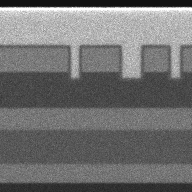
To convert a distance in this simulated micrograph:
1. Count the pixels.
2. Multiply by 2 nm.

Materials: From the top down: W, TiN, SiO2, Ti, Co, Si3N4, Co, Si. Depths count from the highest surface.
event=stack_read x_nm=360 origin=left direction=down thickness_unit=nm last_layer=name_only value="W 76, TiN 70, Ti 54, Co 44, Si3N4 68, Co 38, Si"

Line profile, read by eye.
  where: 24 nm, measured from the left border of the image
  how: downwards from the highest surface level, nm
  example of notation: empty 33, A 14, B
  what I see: W 74, TiN 6, SiO2 48, Ti 72, Co 44, Si3N4 68, Co 38, Si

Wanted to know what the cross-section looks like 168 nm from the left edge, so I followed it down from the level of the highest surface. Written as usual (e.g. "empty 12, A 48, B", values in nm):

W 74, TiN 6, SiO2 48, Ti 72, Co 44, Si3N4 68, Co 38, Si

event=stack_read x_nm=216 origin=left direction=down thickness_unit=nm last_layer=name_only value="W 74, TiN 6, SiO2 48, Ti 72, Co 44, Si3N4 68, Co 38, Si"